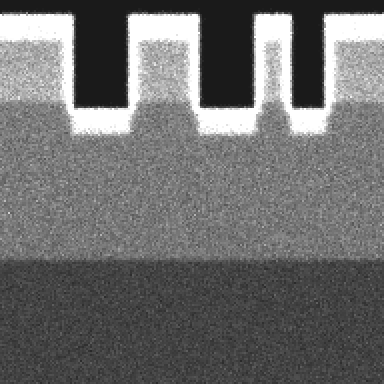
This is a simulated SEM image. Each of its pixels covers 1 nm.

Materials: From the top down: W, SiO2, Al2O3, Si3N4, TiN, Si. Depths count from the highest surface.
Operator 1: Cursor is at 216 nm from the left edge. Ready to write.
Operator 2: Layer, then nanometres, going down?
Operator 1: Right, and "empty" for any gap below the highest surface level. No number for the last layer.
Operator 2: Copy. empty 94, W 24, Si3N4 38, TiN 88, Si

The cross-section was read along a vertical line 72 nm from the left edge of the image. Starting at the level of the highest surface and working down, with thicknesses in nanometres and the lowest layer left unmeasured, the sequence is empty 94, W 24, Si3N4 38, TiN 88, Si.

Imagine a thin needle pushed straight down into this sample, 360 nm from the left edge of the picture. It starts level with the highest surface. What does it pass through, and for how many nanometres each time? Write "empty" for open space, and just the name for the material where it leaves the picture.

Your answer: W 24, SiO2 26, Al2O3 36, Si3N4 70, TiN 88, Si